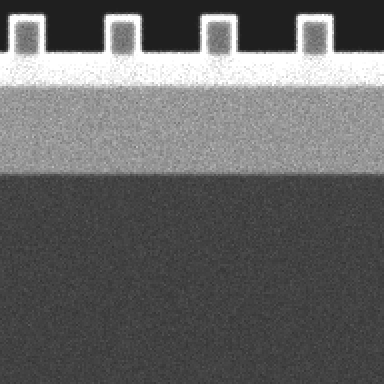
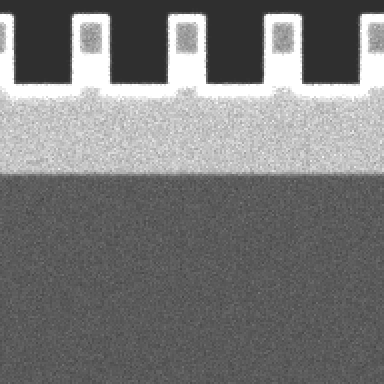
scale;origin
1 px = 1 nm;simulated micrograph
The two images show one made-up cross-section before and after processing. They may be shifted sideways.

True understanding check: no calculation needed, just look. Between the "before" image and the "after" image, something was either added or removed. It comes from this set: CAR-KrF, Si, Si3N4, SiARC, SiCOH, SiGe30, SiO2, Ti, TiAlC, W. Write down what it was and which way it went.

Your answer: W (removed)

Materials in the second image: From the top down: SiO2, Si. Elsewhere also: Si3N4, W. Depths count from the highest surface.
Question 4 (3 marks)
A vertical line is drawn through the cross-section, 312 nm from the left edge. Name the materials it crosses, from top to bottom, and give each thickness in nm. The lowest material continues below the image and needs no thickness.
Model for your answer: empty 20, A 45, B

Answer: empty 70, SiO2 88, Si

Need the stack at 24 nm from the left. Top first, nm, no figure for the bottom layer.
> empty 70, SiO2 88, Si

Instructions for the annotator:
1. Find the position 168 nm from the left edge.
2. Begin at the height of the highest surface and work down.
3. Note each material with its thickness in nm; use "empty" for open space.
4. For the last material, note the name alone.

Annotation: empty 70, SiO2 88, Si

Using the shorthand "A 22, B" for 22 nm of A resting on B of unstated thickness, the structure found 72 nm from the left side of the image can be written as empty 70, SiO2 88, Si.